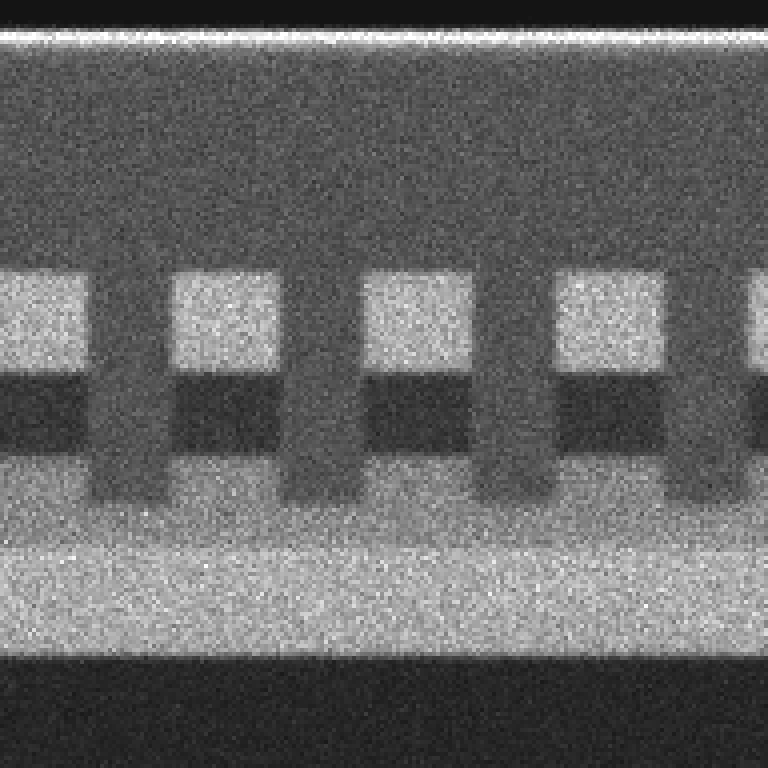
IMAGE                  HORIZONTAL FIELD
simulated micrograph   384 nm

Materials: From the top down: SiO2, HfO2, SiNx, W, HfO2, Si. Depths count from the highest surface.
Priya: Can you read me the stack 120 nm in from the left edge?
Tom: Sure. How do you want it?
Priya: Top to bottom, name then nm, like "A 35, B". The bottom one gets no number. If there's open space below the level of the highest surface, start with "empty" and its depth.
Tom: SiO2 120, HfO2 50, SiNx 42, W 46, HfO2 54, Si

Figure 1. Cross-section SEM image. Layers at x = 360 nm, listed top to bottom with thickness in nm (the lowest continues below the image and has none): SiO2 236, W 22, HfO2 54, Si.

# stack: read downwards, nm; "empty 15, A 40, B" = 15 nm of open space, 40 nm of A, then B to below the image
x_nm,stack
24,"SiO2 120, HfO2 50, SiNx 42, W 46, HfO2 54, Si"